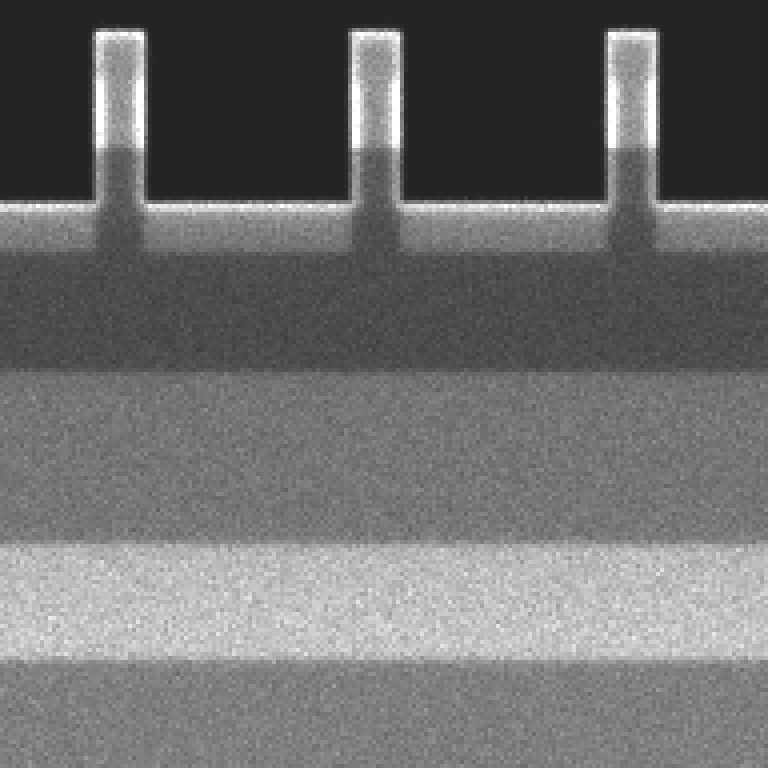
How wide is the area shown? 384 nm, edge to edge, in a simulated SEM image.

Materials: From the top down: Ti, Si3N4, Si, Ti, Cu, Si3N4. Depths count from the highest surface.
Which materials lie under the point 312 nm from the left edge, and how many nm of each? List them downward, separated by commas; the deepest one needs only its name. Ti 24, Si3N4 34, Si 112, Ti 86, Cu 58, Si3N4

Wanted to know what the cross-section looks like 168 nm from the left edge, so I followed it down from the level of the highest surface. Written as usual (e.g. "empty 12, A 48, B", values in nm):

empty 86, Ti 24, Si 60, Ti 86, Cu 58, Si3N4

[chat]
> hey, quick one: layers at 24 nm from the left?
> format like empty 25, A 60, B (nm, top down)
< empty 86, Ti 24, Si 60, Ti 86, Cu 58, Si3N4